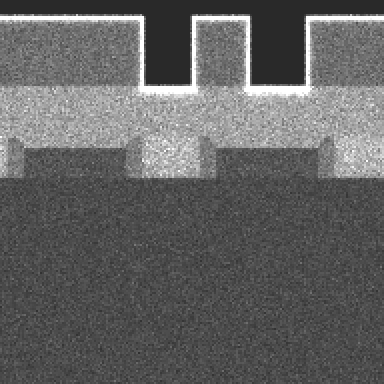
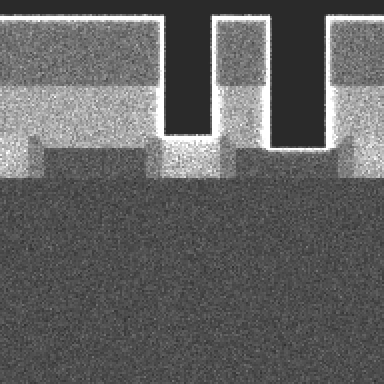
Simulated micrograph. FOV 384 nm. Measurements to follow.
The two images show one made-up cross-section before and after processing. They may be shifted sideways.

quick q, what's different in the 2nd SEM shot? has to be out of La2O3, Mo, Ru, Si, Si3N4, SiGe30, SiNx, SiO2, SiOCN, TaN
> SiO2 removed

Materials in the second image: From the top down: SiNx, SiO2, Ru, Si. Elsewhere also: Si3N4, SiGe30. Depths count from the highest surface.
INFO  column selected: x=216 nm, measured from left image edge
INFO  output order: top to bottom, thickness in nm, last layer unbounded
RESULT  SiNx 70, SiO2 50, Ru 42, Si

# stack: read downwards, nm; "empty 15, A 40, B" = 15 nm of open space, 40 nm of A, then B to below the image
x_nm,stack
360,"SiNx 70, SiO2 50, Ru 42, Si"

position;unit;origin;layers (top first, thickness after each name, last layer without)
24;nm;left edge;SiNx 70, SiO2 50, Ru 42, Si